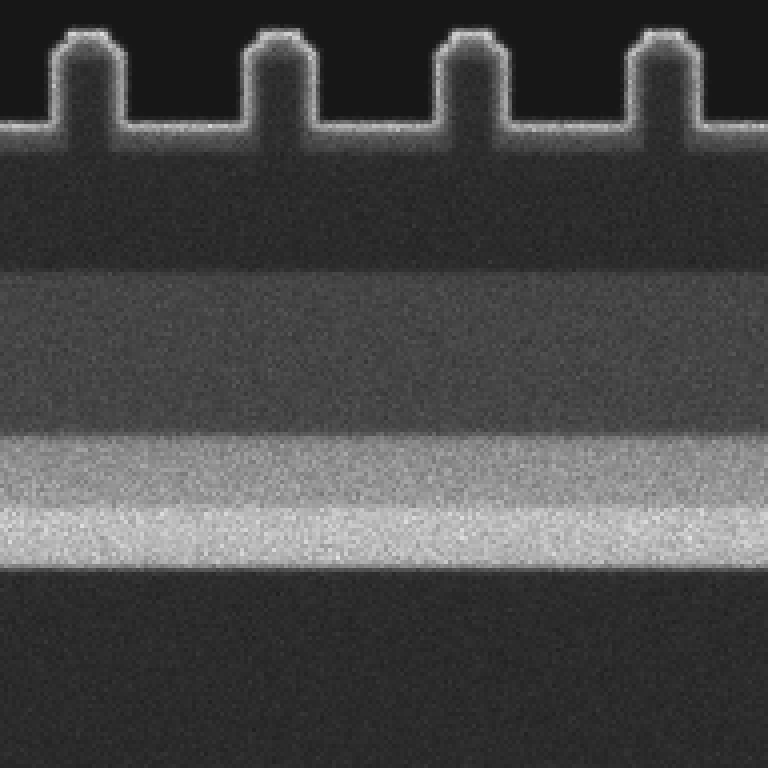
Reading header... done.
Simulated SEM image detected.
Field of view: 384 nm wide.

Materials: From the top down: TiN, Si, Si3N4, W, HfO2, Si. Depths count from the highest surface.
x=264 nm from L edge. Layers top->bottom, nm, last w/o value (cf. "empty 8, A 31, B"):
empty 46, TiN 14, Si 60, Si3N4 82, W 36, HfO2 30, Si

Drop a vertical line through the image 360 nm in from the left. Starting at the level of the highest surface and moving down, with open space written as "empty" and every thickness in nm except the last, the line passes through empty 46, TiN 14, Si 60, Si3N4 82, W 36, HfO2 30, Si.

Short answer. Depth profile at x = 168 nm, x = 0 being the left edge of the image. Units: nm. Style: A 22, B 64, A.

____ empty 46, TiN 14, Si 60, Si3N4 82, W 36, HfO2 30, Si